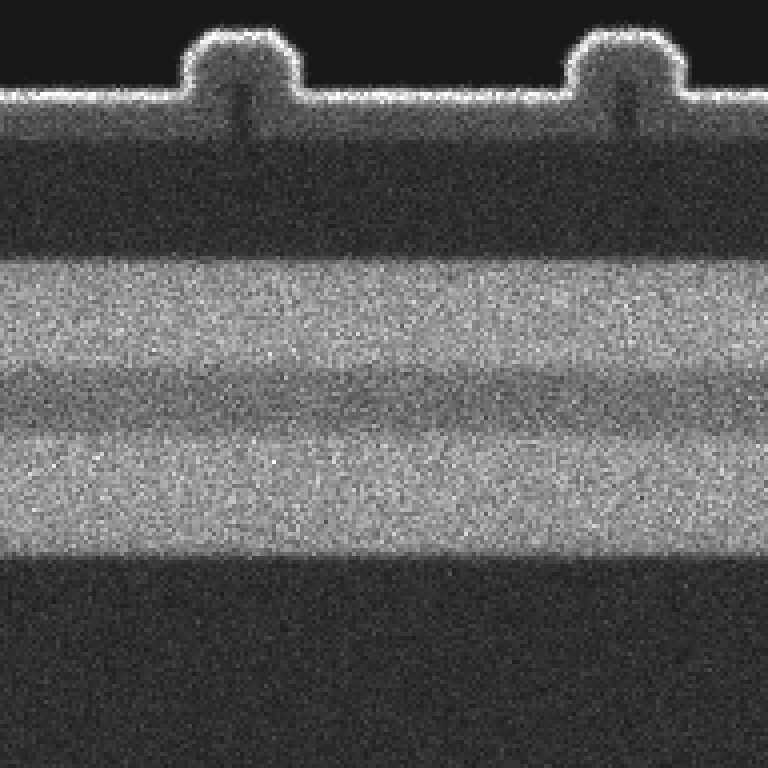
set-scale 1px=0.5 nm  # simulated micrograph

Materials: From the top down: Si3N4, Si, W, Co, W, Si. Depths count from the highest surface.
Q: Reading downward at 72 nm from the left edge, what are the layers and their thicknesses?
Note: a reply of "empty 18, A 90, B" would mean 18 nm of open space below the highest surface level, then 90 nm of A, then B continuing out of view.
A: empty 30, Si3N4 24, Si 60, W 54, Co 34, W 60, Si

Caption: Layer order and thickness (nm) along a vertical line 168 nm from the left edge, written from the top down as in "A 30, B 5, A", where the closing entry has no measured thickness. empty 30, Si3N4 24, Si 60, W 54, Co 34, W 60, Si